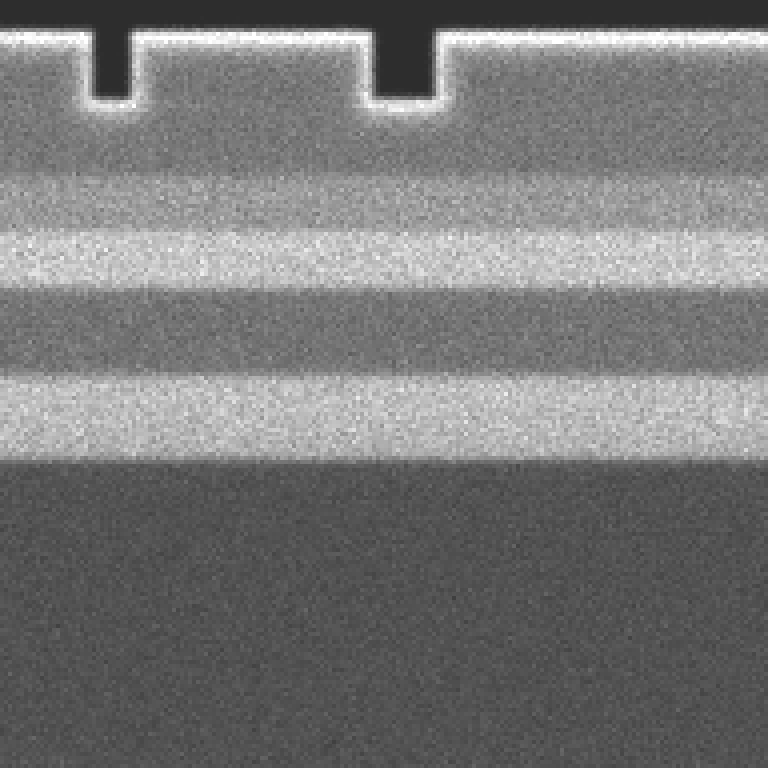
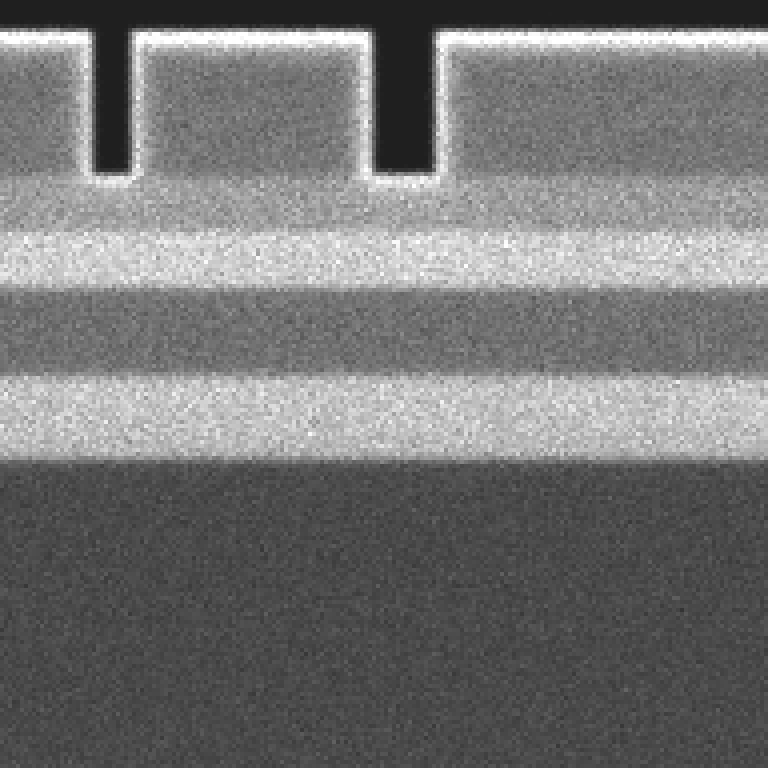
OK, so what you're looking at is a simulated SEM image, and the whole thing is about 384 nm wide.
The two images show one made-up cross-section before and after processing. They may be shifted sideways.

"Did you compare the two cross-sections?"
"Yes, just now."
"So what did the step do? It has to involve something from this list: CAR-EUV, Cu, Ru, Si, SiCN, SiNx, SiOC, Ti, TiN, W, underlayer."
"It removed underlayer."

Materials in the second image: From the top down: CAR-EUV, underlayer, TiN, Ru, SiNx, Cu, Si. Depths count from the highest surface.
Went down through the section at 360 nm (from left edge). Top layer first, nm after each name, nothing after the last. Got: CAR-EUV 34, underlayer 38, TiN 28, Ru 28, SiNx 44, Cu 42, Si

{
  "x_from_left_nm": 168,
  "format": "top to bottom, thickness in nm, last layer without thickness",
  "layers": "CAR-EUV 34, underlayer 38, TiN 28, Ru 28, SiNx 44, Cu 42, Si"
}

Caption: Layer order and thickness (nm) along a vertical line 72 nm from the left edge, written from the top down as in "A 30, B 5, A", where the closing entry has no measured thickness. CAR-EUV 34, underlayer 38, TiN 28, Ru 28, SiNx 44, Cu 42, Si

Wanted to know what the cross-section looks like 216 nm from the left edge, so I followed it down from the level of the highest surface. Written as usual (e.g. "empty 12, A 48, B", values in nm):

empty 72, TiN 28, Ru 28, SiNx 44, Cu 42, Si